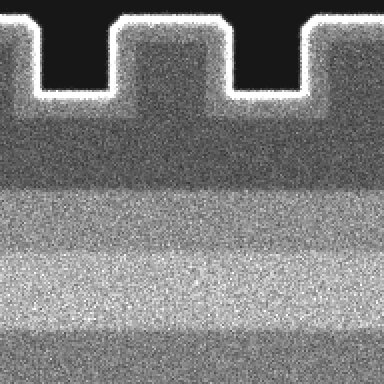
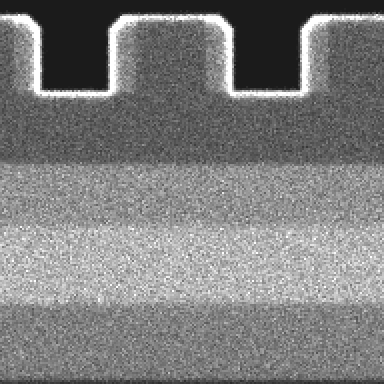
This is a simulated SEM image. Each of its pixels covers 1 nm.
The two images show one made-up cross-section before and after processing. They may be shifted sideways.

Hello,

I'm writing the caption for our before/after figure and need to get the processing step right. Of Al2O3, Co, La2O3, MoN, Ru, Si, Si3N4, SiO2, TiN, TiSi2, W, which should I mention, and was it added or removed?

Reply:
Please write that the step removed Al2O3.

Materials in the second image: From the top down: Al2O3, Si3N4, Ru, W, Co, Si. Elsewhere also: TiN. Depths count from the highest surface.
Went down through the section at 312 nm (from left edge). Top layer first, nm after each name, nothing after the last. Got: empty 2, Al2O3 74, Si3N4 72, Ru 62, W 78, Co 76, Si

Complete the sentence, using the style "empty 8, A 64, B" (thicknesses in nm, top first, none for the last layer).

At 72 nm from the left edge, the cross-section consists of empty 76, Si3N4 72, Ru 62, W 78, Co 76, Si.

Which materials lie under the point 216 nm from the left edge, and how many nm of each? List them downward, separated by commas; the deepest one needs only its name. Al2O3 76, Si3N4 72, Ru 62, W 78, Co 76, Si